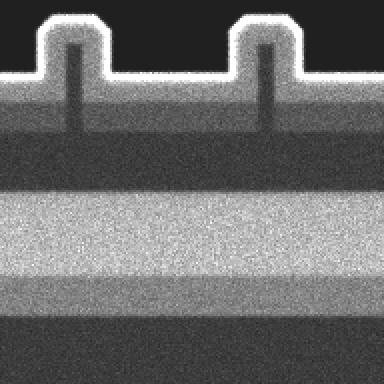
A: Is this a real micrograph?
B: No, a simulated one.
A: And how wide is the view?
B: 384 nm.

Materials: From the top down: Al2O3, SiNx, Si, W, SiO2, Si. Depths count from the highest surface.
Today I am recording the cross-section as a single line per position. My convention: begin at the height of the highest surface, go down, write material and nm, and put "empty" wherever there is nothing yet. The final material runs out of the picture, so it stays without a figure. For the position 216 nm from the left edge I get empty 58, Al2O3 28, SiNx 30, Si 60, W 84, SiO2 40, Si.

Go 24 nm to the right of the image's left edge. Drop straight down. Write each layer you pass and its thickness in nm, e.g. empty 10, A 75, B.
empty 58, Al2O3 28, SiNx 30, Si 60, W 84, SiO2 40, Si